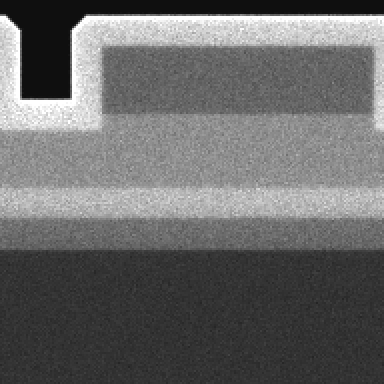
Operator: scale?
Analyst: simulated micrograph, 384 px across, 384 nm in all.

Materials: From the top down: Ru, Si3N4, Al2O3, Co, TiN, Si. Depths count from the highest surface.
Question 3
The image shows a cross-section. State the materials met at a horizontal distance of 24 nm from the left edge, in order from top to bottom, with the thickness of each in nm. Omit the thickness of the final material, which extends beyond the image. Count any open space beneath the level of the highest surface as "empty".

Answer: empty 84, Ru 30, Al2O3 58, Co 30, TiN 32, Si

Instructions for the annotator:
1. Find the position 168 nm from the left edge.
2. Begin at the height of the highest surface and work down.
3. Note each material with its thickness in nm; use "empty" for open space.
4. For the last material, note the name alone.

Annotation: Ru 30, Si3N4 68, Al2O3 74, Co 30, TiN 32, Si